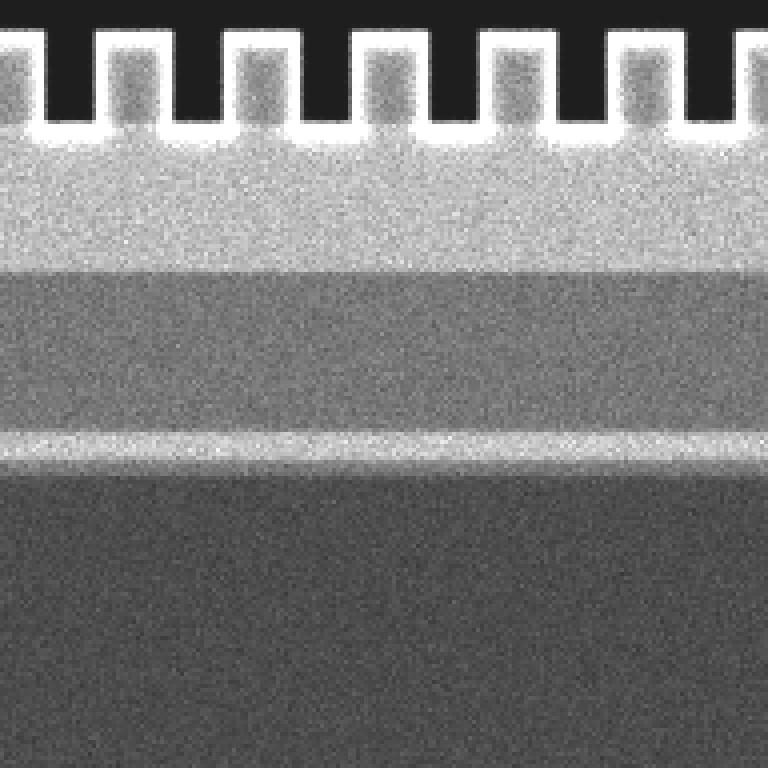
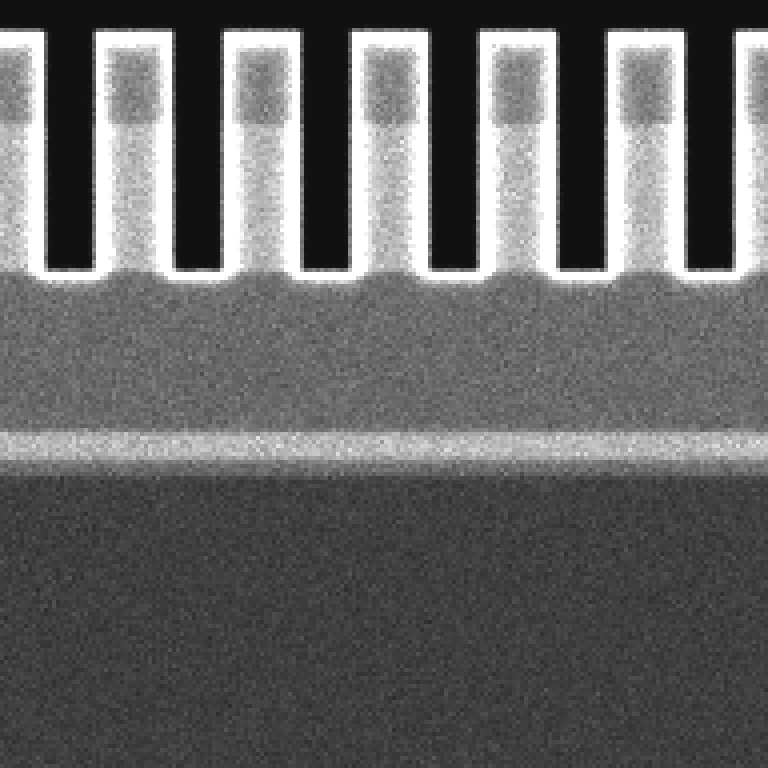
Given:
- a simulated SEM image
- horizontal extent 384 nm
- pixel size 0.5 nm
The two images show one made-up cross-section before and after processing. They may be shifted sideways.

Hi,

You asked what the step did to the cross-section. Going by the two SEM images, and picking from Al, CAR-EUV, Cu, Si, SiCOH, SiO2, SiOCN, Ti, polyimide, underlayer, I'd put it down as SiO2, removed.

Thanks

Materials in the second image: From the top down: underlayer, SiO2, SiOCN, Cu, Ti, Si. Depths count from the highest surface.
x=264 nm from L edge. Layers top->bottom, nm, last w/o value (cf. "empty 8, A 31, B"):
underlayer 46, SiO2 74, SiOCN 80, Cu 14, Ti 8, Si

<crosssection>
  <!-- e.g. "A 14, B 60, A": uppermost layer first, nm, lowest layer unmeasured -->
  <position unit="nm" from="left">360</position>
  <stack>empty 120, SiOCN 80, Cu 14, Ti 8, Si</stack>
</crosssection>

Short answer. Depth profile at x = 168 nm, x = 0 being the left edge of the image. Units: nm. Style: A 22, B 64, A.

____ empty 120, SiOCN 80, Cu 14, Ti 8, Si